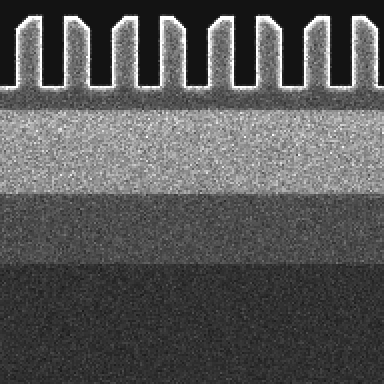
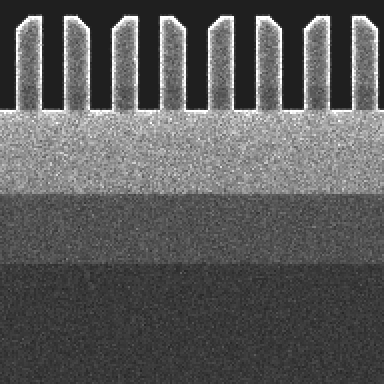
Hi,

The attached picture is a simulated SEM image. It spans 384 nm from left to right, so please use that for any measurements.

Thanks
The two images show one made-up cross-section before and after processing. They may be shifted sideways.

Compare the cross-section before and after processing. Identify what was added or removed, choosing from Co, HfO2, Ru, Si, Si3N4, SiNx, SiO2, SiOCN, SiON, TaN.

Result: SiOCN removed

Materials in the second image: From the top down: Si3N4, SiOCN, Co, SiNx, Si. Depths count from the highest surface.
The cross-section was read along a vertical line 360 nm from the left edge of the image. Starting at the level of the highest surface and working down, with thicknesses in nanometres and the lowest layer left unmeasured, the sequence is Si3N4 70, SiOCN 24, Co 84, SiNx 70, Si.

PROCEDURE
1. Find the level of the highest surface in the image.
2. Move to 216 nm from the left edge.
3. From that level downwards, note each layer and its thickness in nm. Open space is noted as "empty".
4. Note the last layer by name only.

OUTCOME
empty 4, Si3N4 66, SiOCN 24, Co 84, SiNx 70, Si